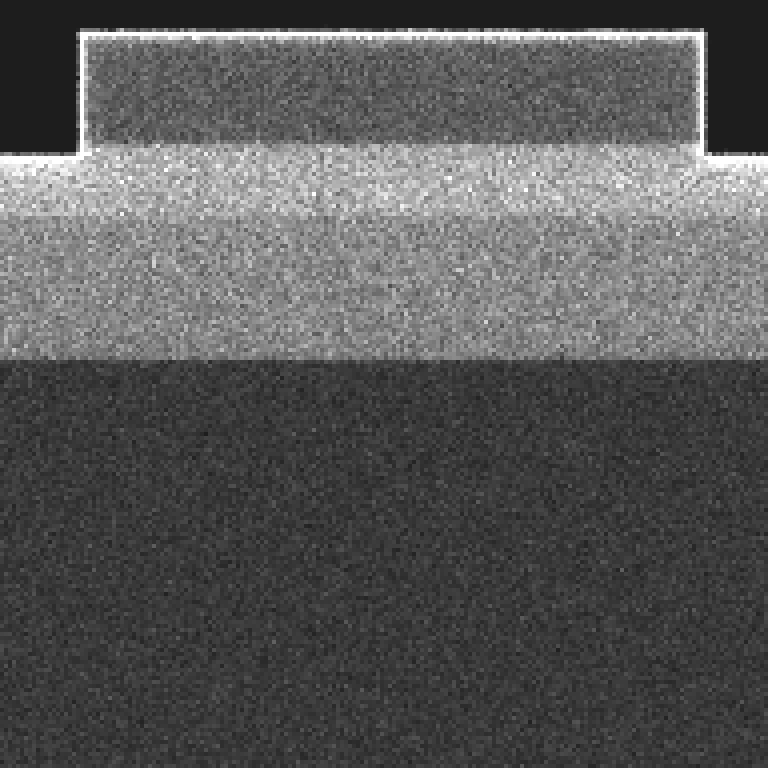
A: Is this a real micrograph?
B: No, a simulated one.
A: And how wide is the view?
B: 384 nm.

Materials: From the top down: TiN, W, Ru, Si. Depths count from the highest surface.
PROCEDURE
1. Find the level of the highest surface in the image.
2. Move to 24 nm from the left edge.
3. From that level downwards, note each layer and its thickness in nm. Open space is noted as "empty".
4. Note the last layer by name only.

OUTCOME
empty 62, W 30, Ru 72, Si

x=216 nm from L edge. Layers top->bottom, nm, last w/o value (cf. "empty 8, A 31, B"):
TiN 56, W 36, Ru 72, Si